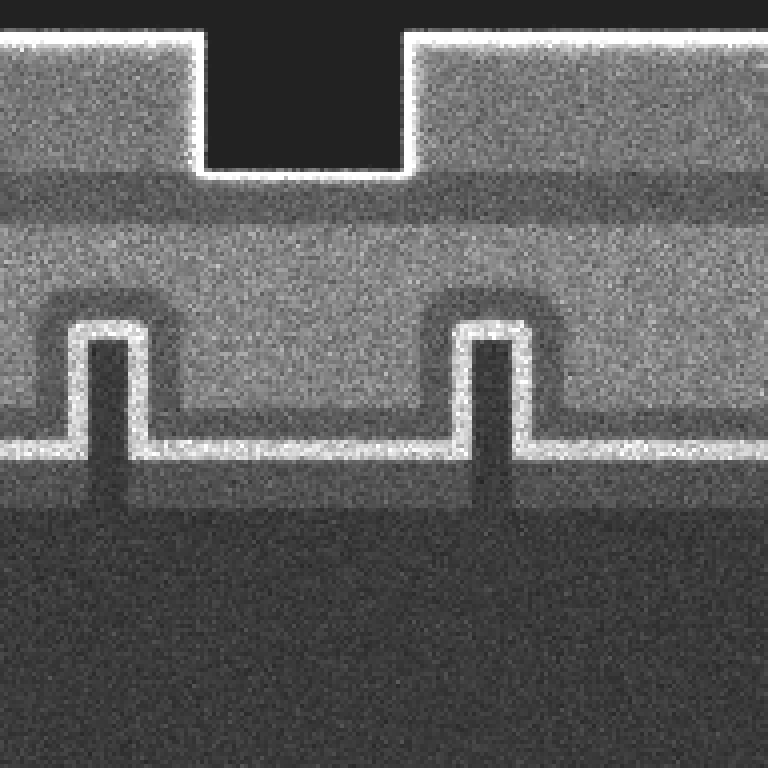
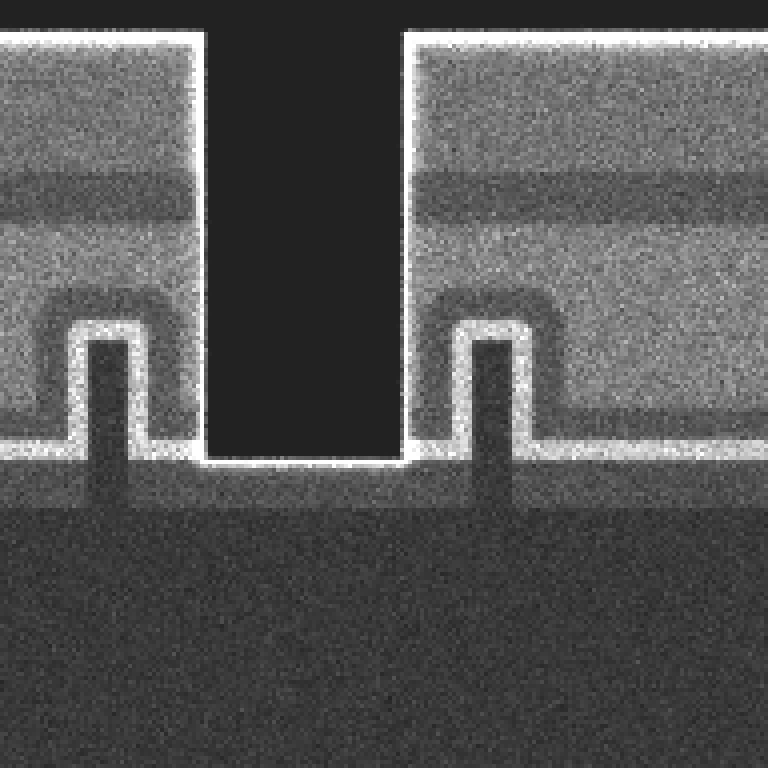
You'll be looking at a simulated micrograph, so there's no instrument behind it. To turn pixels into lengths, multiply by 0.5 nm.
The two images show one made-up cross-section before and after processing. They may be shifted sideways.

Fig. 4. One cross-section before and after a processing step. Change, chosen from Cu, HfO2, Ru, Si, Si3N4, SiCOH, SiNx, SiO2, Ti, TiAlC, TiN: HfO2 and Ru and Si3N4 and TiN removed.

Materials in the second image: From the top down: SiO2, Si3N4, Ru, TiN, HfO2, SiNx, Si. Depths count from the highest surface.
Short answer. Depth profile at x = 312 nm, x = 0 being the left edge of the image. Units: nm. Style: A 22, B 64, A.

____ SiO2 70, Si3N4 26, Ru 92, TiN 16, HfO2 10, SiNx 24, Si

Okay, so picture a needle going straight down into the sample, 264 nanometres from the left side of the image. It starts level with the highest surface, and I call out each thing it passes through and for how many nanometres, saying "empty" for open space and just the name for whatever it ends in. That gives SiO2 70, Si3N4 26, Ru 32, TiN 20, HfO2 66, SiNx 24, Si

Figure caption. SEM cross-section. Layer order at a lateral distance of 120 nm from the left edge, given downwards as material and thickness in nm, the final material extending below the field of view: empty 214, SiNx 24, Si